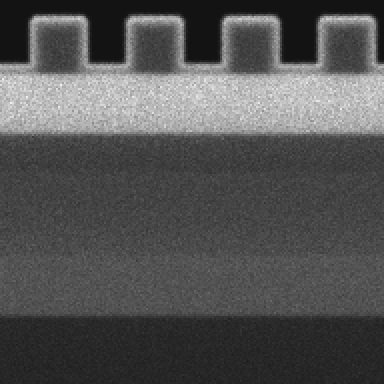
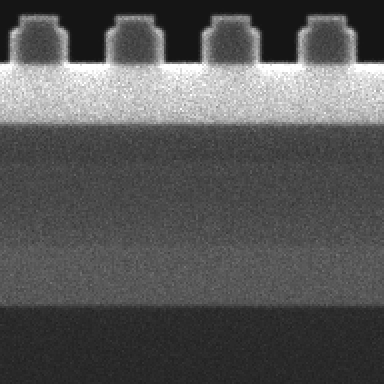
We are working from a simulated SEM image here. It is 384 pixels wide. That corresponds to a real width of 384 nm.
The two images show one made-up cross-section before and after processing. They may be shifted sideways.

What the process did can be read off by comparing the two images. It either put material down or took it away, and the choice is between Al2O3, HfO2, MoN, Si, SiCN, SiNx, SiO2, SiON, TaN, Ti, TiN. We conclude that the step removed SiO2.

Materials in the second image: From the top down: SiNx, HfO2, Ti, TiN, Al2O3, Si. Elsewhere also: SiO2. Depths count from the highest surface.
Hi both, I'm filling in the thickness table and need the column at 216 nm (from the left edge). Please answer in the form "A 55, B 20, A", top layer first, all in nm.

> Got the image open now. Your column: SiNx 48, HfO2 60, Ti 38, TiN 84, Al2O3 60, Si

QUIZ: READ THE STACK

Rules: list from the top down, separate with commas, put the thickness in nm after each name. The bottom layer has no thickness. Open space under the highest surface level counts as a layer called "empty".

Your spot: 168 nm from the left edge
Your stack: empty 48, HfO2 60, Ti 38, TiN 84, Al2O3 60, Si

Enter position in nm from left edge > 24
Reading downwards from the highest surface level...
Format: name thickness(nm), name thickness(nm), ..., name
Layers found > SiNx 48, HfO2 60, Ti 38, TiN 84, Al2O3 60, Si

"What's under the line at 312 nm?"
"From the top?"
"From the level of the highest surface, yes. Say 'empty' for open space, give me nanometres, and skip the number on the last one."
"SiNx 48, HfO2 60, Ti 38, TiN 84, Al2O3 60, Si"